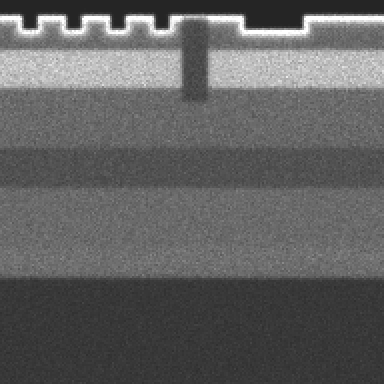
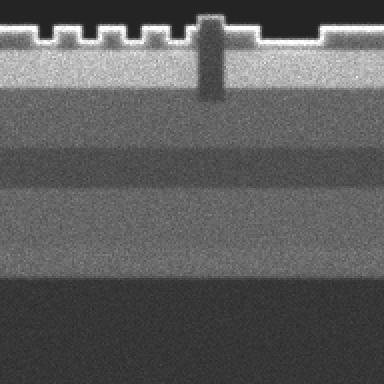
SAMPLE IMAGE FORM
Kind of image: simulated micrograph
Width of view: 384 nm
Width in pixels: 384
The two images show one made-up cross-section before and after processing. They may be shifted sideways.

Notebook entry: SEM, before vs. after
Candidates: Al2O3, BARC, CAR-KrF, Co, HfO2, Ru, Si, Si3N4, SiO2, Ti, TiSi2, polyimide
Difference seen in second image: SiO2 removed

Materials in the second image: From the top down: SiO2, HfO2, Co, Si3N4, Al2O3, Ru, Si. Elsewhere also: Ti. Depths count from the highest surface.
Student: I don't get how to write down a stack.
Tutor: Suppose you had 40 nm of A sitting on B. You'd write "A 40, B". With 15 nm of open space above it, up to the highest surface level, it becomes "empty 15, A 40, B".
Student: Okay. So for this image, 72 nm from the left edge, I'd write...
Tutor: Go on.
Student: empty 10, SiO2 24, HfO2 38, Co 60, Si3N4 40, Al2O3 60, Ru 30, Si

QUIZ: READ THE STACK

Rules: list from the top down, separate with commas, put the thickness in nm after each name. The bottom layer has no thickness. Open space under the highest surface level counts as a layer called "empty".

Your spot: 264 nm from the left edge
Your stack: empty 24, SiO2 10, HfO2 38, Co 60, Si3N4 40, Al2O3 60, Ru 30, Si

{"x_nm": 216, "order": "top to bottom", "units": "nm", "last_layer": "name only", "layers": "Ti 86, Co 46, Si3N4 40, Al2O3 60, Ru 30, Si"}